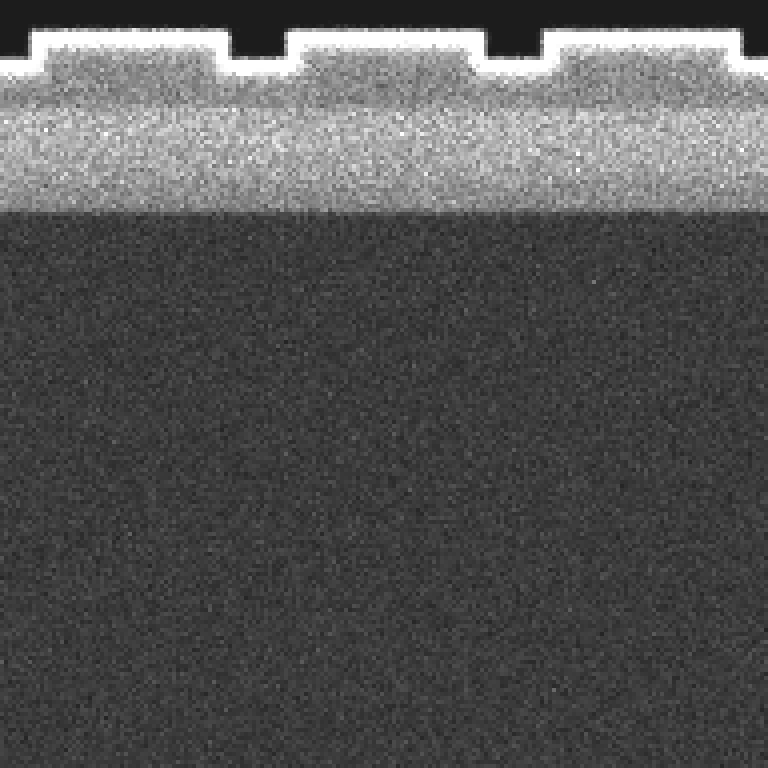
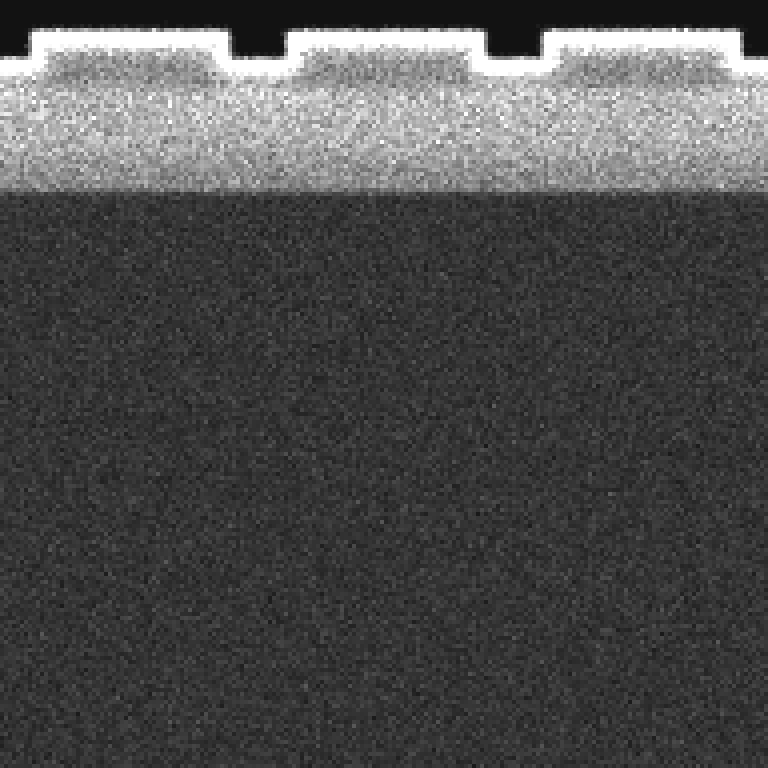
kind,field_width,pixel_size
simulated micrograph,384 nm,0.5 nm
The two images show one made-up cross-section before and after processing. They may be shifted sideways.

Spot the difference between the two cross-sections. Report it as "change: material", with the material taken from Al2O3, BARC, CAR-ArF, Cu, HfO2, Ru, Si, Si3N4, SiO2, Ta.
removed: SiO2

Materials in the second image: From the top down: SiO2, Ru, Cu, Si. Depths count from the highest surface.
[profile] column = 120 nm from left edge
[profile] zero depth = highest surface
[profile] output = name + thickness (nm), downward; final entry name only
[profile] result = empty 14, SiO2 14, Ru 36, Cu 16, Si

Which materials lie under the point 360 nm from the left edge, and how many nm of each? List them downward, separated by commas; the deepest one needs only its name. SiO2 28, Ru 36, Cu 16, Si